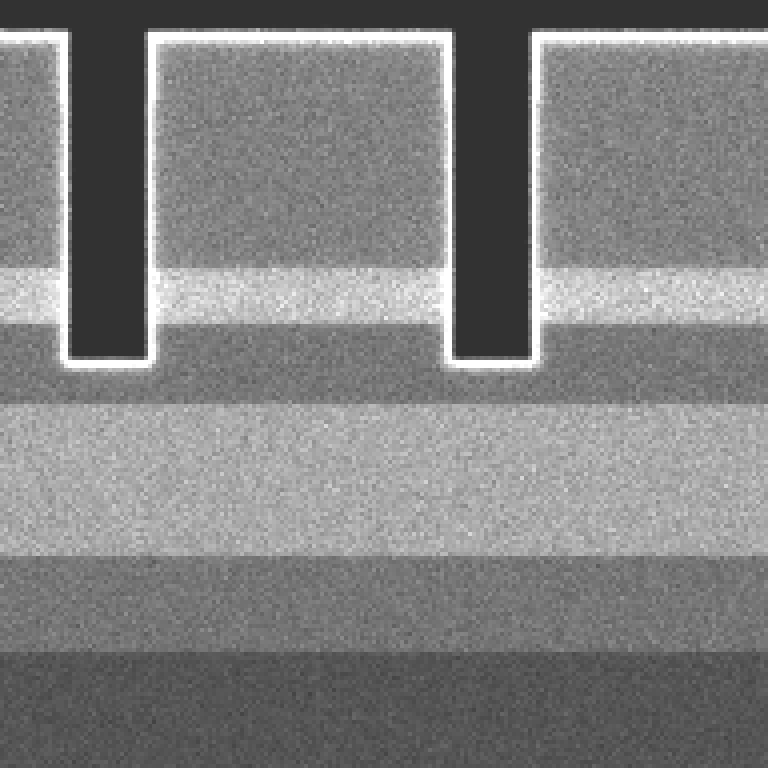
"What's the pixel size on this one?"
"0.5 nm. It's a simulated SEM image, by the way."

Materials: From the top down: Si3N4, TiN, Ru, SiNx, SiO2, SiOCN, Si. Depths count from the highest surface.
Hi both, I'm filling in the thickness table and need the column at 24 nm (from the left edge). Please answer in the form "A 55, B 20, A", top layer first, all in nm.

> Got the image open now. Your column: Si3N4 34, TiN 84, Ru 28, SiNx 40, SiO2 76, SiOCN 48, Si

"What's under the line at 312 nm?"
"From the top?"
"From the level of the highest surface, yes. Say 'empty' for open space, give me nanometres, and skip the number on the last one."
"Si3N4 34, TiN 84, Ru 28, SiNx 40, SiO2 76, SiOCN 48, Si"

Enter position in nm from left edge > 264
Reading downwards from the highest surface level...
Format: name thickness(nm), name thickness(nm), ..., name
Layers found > empty 164, SiNx 22, SiO2 76, SiOCN 48, Si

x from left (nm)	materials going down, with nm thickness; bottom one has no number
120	Si3N4 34, TiN 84, Ru 28, SiNx 40, SiO2 76, SiOCN 48, Si